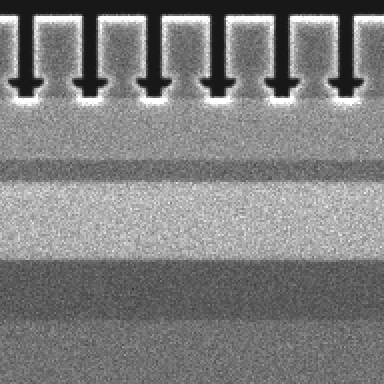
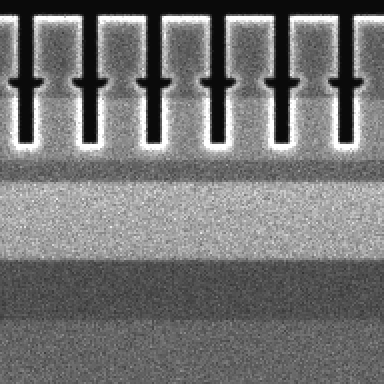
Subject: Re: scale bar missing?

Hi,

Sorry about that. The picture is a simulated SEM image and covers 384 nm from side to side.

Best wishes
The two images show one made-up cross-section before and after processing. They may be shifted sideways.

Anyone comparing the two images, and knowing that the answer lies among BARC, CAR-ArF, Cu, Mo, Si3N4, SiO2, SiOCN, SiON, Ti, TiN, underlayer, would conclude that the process removed SiO2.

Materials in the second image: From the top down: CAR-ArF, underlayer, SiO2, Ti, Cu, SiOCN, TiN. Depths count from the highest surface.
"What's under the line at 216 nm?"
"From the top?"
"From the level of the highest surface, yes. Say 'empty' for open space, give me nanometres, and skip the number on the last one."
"empty 128, SiO2 16, Ti 22, Cu 78, SiOCN 60, TiN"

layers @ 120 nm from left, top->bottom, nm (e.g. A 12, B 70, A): CAR-ArF 62, underlayer 20, SiO2 62, Ti 22, Cu 78, SiOCN 60, TiN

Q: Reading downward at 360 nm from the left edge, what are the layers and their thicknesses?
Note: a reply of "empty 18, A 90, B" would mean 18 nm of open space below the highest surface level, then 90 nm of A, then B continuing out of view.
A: CAR-ArF 62, empty 8, underlayer 12, SiO2 62, Ti 22, Cu 78, SiOCN 60, TiN